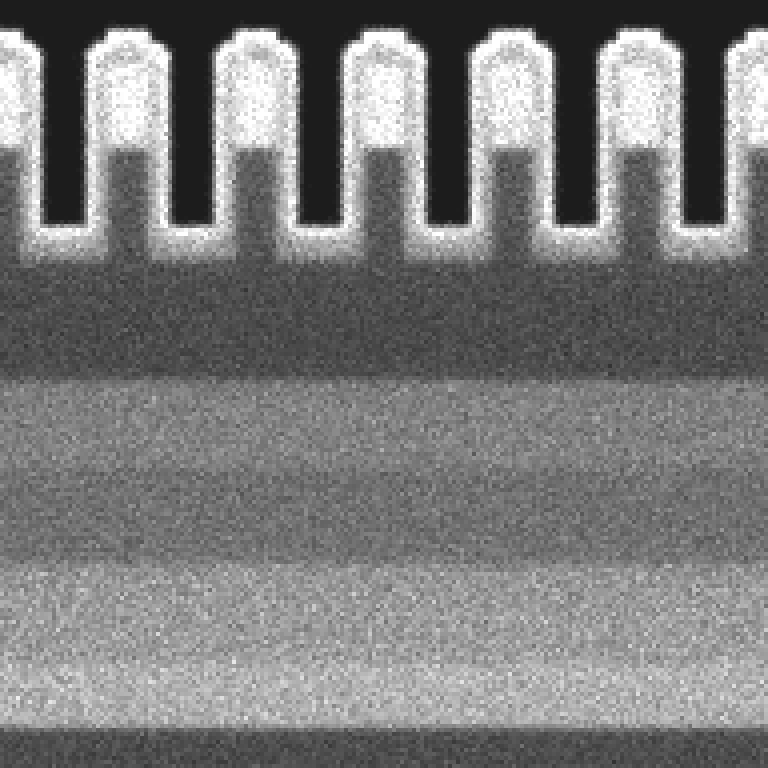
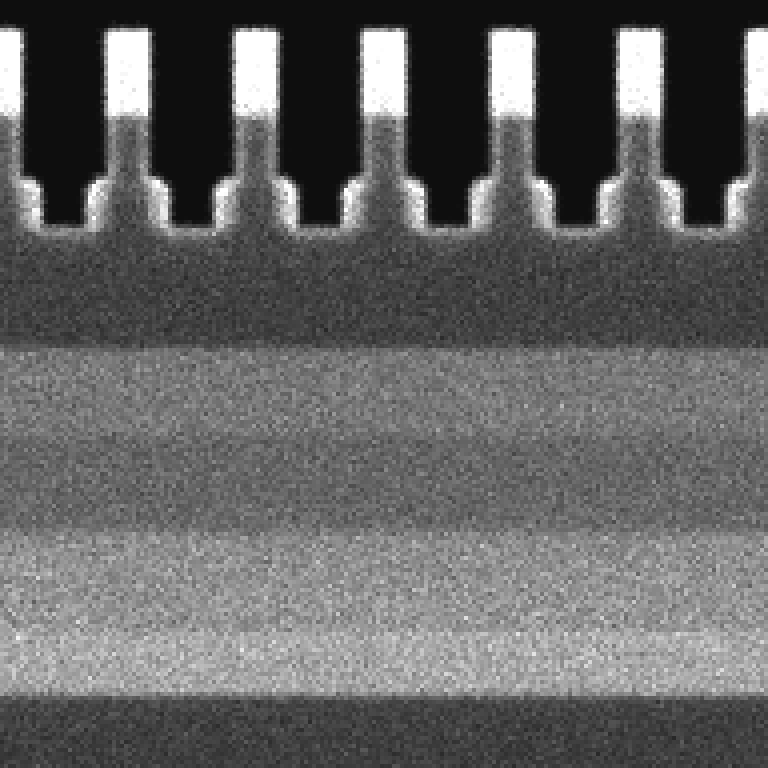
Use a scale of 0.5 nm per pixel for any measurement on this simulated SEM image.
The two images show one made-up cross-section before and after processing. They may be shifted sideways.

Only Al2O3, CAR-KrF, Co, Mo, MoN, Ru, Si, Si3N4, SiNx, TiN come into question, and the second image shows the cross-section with TiN removed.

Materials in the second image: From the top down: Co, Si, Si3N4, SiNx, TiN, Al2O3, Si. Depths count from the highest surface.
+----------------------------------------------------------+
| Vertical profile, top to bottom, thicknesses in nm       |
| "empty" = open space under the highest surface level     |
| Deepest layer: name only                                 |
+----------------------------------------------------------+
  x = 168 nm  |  empty 98, Si 60, Si3N4 44, SiNx 48, TiN 50, Al2O3 32, Si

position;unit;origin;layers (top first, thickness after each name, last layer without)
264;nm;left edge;Co 42, Si 116, Si3N4 44, SiNx 48, TiN 50, Al2O3 32, Si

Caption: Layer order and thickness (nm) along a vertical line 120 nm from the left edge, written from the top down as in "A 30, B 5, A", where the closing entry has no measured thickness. Co 42, Si 116, Si3N4 44, SiNx 48, TiN 50, Al2O3 32, Si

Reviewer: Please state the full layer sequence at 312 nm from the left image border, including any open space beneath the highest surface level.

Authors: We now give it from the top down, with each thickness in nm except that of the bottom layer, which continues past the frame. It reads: Co 42, Si 116, Si3N4 44, SiNx 48, TiN 50, Al2O3 32, Si